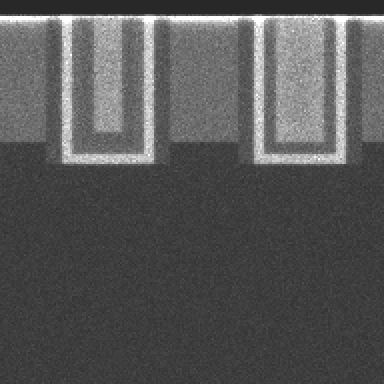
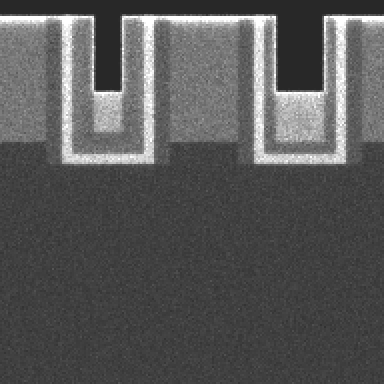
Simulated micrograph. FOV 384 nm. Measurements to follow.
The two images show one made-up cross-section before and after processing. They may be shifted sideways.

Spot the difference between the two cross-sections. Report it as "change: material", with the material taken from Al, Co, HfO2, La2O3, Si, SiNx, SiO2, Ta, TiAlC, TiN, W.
removed: W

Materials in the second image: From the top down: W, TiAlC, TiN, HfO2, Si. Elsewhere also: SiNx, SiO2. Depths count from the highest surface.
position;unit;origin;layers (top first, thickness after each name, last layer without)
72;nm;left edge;TiN 138, HfO2 10, Si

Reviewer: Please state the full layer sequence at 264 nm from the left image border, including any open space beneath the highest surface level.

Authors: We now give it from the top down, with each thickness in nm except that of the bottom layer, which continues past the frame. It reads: TiAlC 138, HfO2 10, Si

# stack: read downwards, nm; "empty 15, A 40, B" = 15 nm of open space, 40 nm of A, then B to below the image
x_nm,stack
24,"SiO2 126, Si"